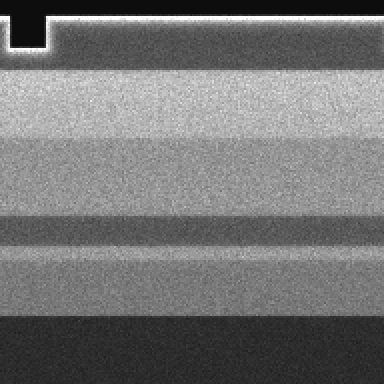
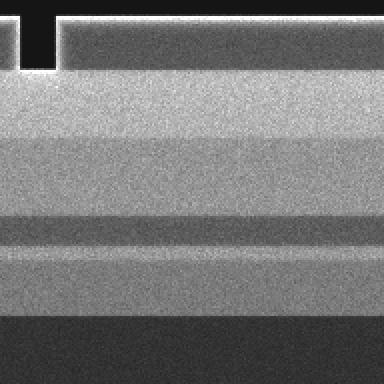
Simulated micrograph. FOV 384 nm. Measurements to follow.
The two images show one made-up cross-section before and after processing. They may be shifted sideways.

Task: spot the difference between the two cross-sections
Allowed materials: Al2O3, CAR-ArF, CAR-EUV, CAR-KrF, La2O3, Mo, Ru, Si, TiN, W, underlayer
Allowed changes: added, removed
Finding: removed underlayer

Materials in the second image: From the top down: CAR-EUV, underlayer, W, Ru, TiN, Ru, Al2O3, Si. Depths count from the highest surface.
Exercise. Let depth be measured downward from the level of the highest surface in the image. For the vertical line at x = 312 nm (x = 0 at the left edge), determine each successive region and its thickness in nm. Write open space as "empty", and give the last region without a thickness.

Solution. CAR-EUV 32, underlayer 22, W 68, Ru 78, TiN 30, Ru 14, Al2O3 56, Si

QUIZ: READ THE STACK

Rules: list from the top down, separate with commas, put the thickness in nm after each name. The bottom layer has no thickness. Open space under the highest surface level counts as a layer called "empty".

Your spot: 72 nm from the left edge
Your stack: CAR-EUV 32, underlayer 22, W 68, Ru 78, TiN 30, Ru 14, Al2O3 56, Si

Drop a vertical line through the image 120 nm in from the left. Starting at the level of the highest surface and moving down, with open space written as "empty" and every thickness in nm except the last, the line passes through CAR-EUV 32, underlayer 22, W 68, Ru 78, TiN 30, Ru 14, Al2O3 56, Si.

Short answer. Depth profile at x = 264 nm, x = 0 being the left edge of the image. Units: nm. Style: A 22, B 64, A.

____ CAR-EUV 32, underlayer 22, W 68, Ru 78, TiN 30, Ru 14, Al2O3 56, Si